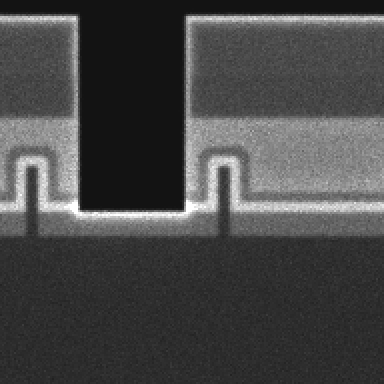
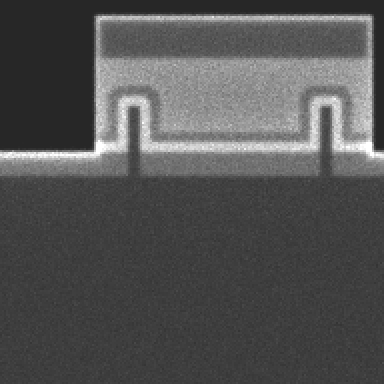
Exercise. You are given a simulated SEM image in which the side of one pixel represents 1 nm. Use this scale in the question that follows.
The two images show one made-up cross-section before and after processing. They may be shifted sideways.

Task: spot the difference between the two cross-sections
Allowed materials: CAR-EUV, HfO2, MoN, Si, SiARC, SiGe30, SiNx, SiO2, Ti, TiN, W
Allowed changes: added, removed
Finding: removed SiARC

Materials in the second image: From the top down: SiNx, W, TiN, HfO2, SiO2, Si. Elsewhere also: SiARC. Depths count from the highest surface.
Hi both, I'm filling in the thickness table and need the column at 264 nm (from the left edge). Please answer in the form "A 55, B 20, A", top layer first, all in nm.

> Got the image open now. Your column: SiNx 42, W 74, TiN 10, HfO2 10, SiO2 24, Si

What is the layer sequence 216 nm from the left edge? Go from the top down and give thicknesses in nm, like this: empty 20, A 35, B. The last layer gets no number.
SiNx 42, W 74, TiN 10, HfO2 10, SiO2 24, Si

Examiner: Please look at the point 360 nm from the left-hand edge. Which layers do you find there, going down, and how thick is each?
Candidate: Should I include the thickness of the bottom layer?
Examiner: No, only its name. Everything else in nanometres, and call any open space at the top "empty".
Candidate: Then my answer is SiNx 42, W 74, TiN 10, HfO2 10, SiO2 24, Si